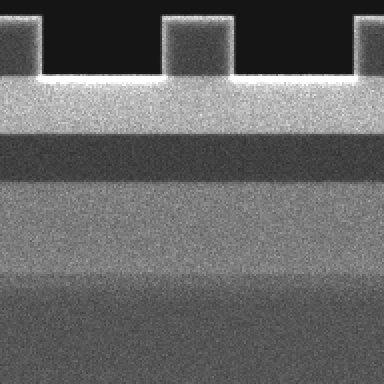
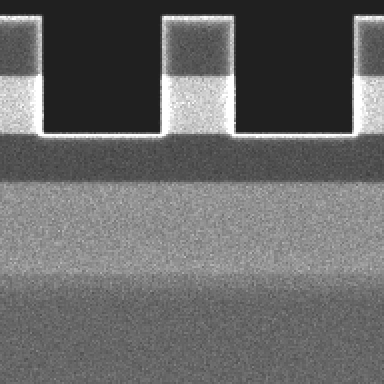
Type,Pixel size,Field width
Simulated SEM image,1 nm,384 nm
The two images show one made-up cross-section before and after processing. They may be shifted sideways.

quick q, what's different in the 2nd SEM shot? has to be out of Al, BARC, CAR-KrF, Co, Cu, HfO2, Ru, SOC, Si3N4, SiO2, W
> HfO2 removed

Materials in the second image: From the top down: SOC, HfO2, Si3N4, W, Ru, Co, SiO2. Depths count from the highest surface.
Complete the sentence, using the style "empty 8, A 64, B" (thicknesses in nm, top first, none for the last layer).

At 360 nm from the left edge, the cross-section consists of SOC 60, HfO2 58, Si3N4 48, W 92, Ru 14, Co 12, SiO2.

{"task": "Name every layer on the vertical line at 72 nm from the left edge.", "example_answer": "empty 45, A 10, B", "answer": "empty 118, Si3N4 48, W 92, Ru 14, Co 12, SiO2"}